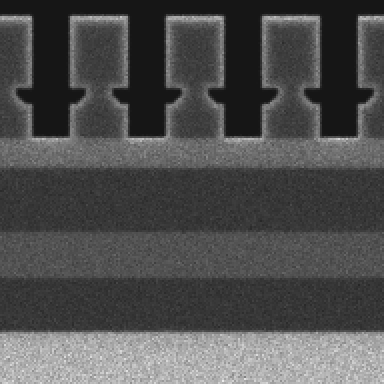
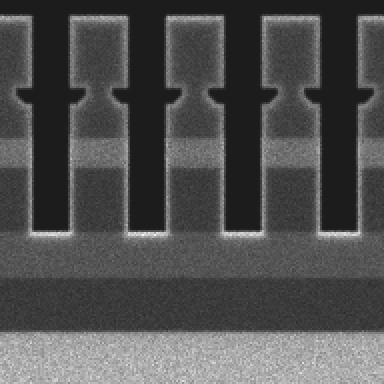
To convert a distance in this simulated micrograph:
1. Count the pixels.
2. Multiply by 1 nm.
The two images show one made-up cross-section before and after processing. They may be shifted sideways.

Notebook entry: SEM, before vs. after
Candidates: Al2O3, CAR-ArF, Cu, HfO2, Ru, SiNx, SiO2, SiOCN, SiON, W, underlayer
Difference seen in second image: Ru and SiNx removed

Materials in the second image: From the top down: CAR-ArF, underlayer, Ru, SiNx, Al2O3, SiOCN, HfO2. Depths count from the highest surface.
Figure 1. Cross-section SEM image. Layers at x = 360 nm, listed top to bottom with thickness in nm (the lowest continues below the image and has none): CAR-ArF 72, empty 16, underlayer 34, Ru 30, SiNx 64, Al2O3 46, SiOCN 54, HfO2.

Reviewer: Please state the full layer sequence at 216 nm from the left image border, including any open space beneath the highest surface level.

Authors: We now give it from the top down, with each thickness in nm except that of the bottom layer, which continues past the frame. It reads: CAR-ArF 72, empty 16, underlayer 34, Ru 30, SiNx 64, Al2O3 46, SiOCN 54, HfO2